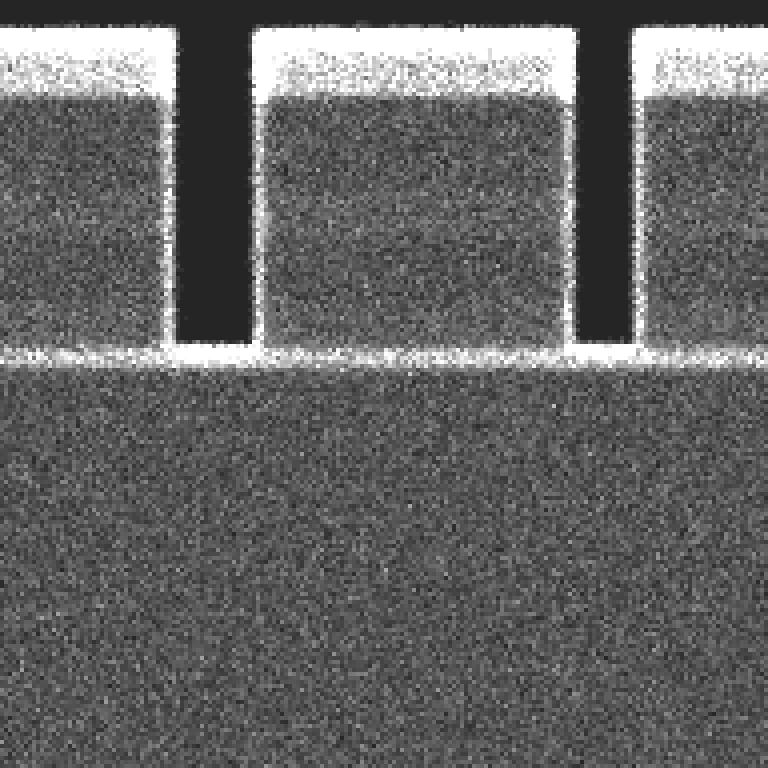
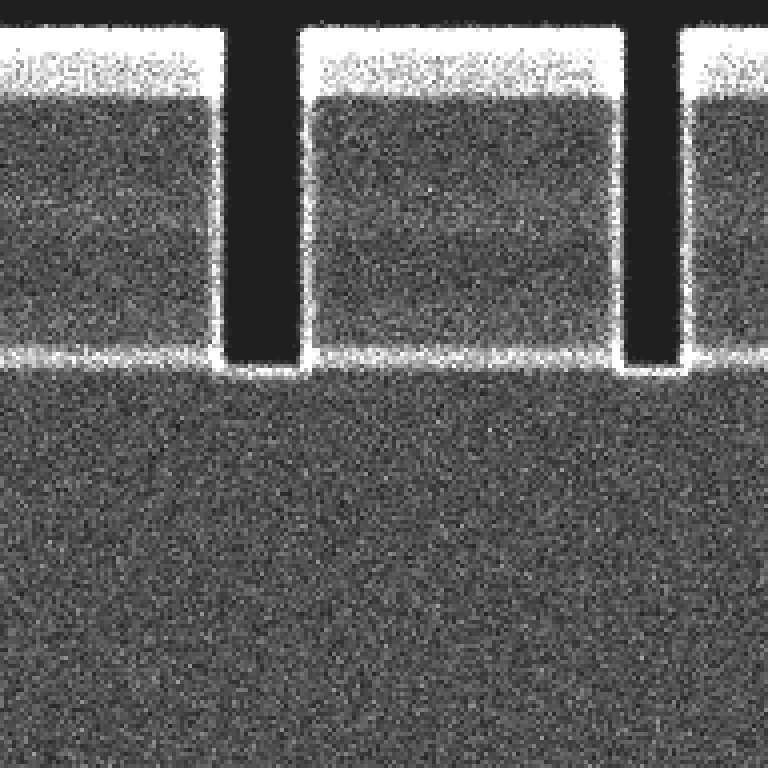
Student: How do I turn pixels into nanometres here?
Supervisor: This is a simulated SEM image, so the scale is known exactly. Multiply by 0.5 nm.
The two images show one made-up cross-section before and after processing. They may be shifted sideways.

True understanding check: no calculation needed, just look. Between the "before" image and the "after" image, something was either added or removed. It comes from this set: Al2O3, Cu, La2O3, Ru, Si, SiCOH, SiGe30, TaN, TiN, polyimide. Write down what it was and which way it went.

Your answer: Ru (removed)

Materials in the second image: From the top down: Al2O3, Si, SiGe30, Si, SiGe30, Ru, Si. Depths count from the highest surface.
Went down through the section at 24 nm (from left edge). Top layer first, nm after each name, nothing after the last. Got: Al2O3 32, Si 46, SiGe30 24, Si 32, SiGe30 24, Ru 10, Si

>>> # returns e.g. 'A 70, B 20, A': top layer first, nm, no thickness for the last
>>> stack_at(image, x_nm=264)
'Al2O3 32, Si 46, SiGe30 24, Si 32, SiGe30 24, Ru 10, Si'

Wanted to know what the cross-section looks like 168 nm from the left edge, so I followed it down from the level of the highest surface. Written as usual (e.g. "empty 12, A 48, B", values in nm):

Al2O3 32, Si 46, SiGe30 24, Si 32, SiGe30 24, Ru 10, Si